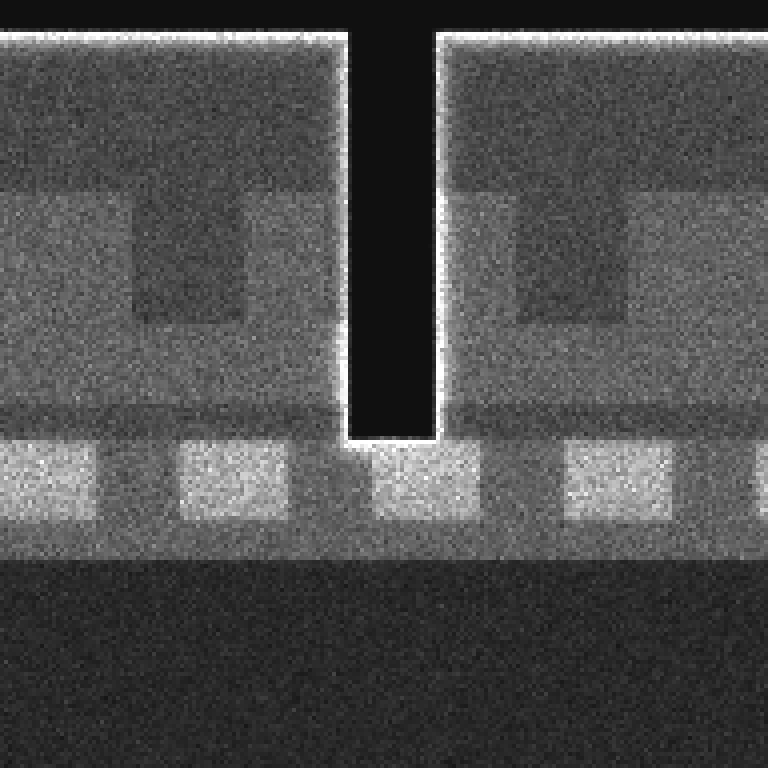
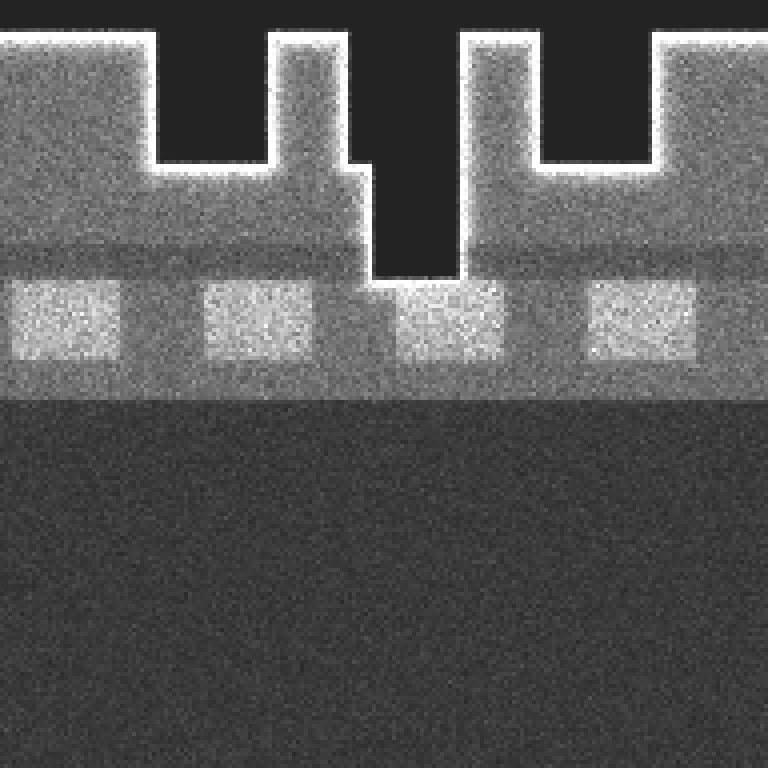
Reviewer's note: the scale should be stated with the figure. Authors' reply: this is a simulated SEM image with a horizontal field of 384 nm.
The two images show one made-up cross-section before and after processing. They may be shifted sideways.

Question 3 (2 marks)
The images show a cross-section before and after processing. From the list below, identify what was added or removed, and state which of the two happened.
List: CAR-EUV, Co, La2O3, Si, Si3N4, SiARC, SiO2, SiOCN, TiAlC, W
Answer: SiARC was removed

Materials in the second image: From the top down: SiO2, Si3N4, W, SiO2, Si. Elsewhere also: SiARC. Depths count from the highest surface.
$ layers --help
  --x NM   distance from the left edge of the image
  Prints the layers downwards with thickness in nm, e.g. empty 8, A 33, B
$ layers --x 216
empty 124, W 40, SiO2 20, Si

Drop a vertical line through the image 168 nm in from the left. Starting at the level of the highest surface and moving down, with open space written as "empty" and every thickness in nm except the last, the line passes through SiO2 106, Si3N4 18, SiO2 60, Si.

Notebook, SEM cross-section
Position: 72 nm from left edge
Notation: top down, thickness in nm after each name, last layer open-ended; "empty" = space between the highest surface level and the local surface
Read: SiO2 106, Si3N4 18, SiO2 60, Si